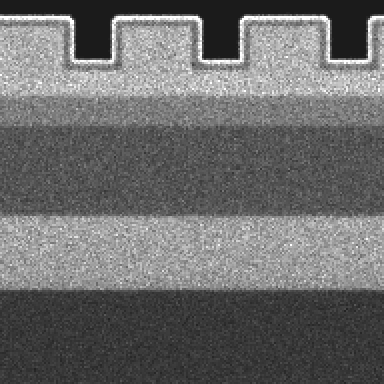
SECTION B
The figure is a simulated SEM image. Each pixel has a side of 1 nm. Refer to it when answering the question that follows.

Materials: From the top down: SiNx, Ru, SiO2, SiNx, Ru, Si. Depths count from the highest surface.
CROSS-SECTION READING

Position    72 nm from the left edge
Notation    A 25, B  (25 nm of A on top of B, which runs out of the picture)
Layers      empty 4, SiNx 50, Ru 26, SiO2 30, SiNx 90, Ru 74, Si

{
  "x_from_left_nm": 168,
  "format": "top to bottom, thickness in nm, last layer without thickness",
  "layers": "SiNx 10, Ru 70, SiO2 30, SiNx 90, Ru 74, Si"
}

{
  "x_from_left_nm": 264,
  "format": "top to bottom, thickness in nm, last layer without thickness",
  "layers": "SiNx 10, Ru 70, SiO2 30, SiNx 90, Ru 74, Si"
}